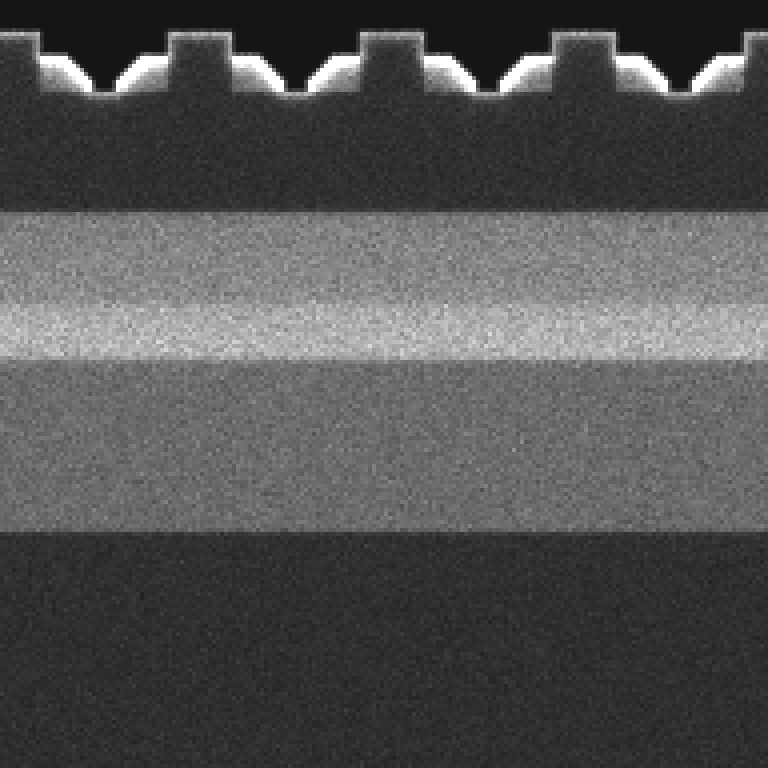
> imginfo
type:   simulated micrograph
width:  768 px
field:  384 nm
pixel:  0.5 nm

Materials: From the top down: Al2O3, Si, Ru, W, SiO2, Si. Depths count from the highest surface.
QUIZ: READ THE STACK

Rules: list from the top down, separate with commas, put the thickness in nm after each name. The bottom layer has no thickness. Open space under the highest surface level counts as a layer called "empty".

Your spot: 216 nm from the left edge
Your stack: empty 12, Al2O3 18, Si 60, Ru 46, W 28, SiO2 86, Si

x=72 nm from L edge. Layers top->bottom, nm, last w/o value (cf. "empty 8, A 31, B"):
empty 12, Al2O3 18, Si 60, Ru 46, W 28, SiO2 86, Si